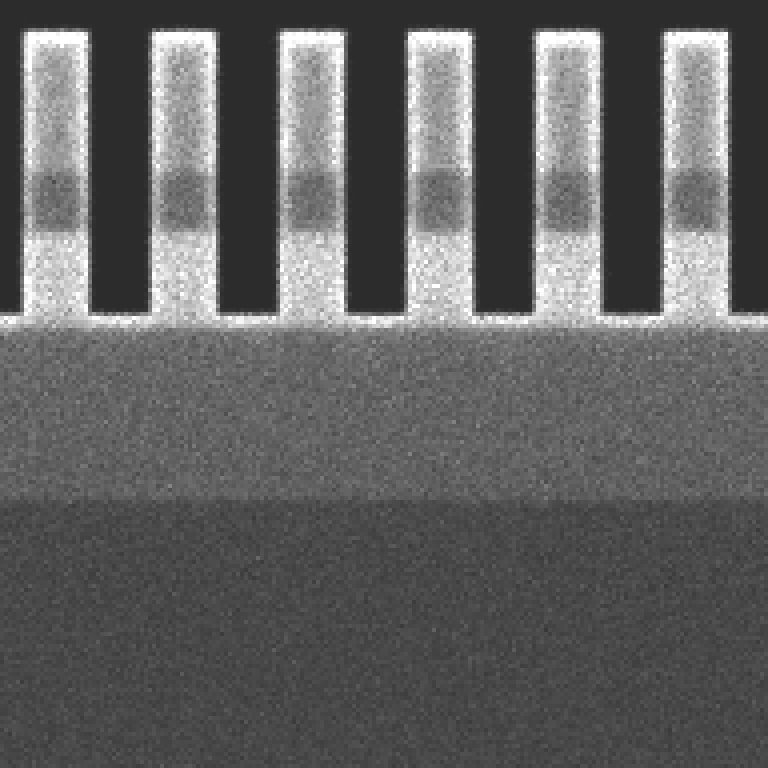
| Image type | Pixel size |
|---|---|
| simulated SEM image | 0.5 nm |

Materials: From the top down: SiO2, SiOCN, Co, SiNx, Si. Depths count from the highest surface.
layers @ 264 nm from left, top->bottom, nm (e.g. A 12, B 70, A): empty 142, Co 6, SiNx 86, Si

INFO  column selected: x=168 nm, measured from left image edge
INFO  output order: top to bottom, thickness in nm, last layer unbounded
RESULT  SiO2 70, SiOCN 30, Co 48, SiNx 86, Si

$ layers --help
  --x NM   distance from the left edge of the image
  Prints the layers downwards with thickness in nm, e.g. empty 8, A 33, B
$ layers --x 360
SiO2 70, SiOCN 30, Co 48, SiNx 86, Si